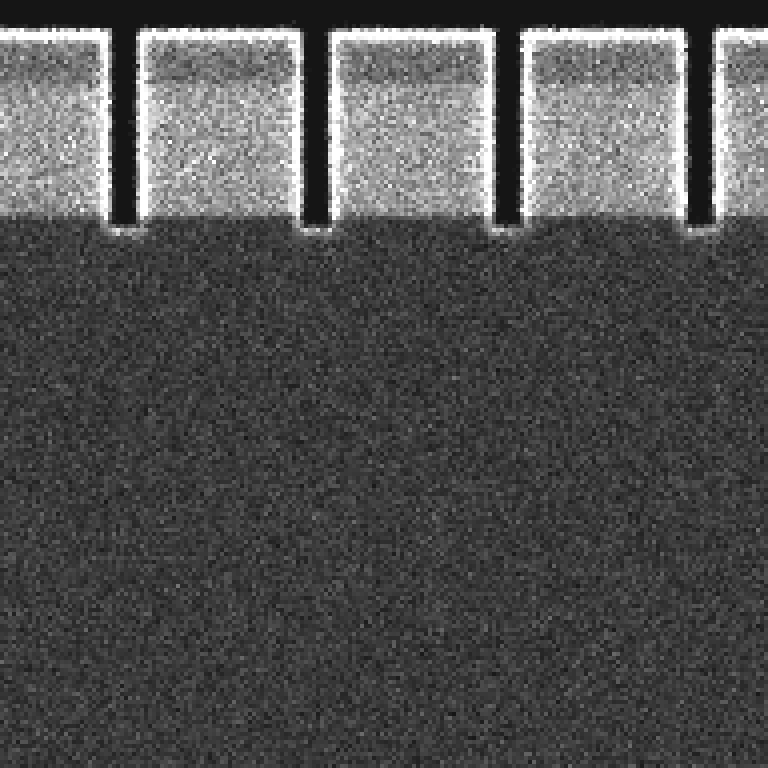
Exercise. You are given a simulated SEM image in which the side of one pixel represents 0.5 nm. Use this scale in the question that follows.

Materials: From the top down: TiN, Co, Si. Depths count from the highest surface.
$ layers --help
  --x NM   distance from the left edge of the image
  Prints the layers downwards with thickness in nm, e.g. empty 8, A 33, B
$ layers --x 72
TiN 26, Co 66, Si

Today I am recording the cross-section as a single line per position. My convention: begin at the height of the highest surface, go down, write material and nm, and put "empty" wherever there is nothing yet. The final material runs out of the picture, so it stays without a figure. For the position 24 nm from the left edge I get TiN 26, Co 66, Si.